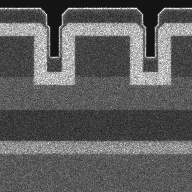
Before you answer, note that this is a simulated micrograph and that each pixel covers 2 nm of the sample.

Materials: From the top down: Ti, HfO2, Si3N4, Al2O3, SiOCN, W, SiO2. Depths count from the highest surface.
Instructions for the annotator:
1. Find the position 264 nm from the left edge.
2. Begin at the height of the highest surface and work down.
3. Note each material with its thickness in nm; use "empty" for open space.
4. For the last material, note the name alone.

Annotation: Ti 30, HfO2 124, Al2O3 50, SiOCN 62, W 26, SiO2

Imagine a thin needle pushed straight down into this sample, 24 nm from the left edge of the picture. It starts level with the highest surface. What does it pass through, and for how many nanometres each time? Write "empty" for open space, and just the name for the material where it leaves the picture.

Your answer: Ti 30, HfO2 26, Si3N4 82, Al2O3 66, SiOCN 62, W 26, SiO2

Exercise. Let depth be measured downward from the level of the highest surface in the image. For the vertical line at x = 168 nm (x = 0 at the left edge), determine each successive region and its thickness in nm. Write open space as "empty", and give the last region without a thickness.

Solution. Ti 30, HfO2 26, Si3N4 82, Al2O3 66, SiOCN 62, W 26, SiO2